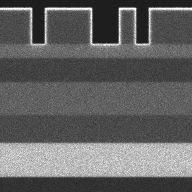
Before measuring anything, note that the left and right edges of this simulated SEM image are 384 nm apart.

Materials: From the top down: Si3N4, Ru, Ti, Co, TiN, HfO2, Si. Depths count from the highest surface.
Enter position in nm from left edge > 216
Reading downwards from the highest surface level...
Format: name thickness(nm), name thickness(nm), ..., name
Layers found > empty 72, Ru 28, Ti 48, Co 66, TiN 56, HfO2 68, Si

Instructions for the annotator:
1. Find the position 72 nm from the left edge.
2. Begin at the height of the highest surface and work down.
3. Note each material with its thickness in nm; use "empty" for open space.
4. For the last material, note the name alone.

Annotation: empty 72, Ru 28, Ti 48, Co 66, TiN 56, HfO2 68, Si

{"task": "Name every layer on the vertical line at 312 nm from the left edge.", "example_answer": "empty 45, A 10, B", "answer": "Si3N4 72, Ru 28, Ti 48, Co 66, TiN 56, HfO2 68, Si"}